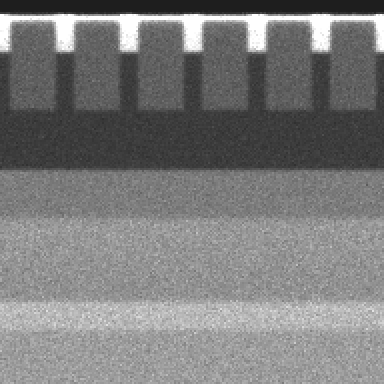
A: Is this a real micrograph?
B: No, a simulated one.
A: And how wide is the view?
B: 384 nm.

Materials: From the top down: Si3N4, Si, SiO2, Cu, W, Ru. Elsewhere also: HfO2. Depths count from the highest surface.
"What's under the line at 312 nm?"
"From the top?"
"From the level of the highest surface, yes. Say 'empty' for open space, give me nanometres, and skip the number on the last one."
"HfO2 36, Si 118, SiO2 48, Cu 84, W 28, Ru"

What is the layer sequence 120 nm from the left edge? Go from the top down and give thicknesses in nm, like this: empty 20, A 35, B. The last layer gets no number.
HfO2 36, Si 118, SiO2 48, Cu 84, W 28, Ru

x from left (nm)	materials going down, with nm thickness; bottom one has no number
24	Si3N4 94, Si 60, SiO2 48, Cu 84, W 28, Ru